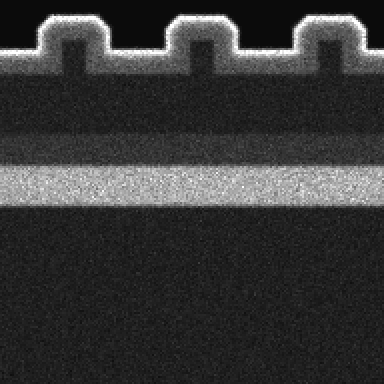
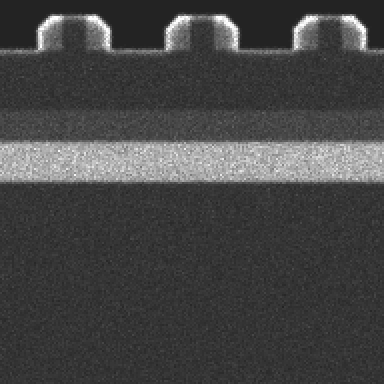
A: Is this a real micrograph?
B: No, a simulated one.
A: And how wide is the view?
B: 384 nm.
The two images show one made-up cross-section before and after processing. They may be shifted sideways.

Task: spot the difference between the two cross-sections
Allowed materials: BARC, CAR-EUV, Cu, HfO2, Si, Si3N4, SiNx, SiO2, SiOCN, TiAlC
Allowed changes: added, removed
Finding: removed SiO2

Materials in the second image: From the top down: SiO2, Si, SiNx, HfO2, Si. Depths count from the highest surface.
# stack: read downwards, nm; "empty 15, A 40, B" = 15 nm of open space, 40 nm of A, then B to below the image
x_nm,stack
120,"empty 34, Si 60, SiNx 32, HfO2 40, Si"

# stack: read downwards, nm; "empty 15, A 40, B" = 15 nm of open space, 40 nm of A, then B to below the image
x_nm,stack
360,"empty 8, SiO2 26, Si 60, SiNx 32, HfO2 40, Si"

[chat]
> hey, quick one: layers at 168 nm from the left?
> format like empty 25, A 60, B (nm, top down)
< empty 10, SiO2 24, Si 60, SiNx 32, HfO2 40, Si